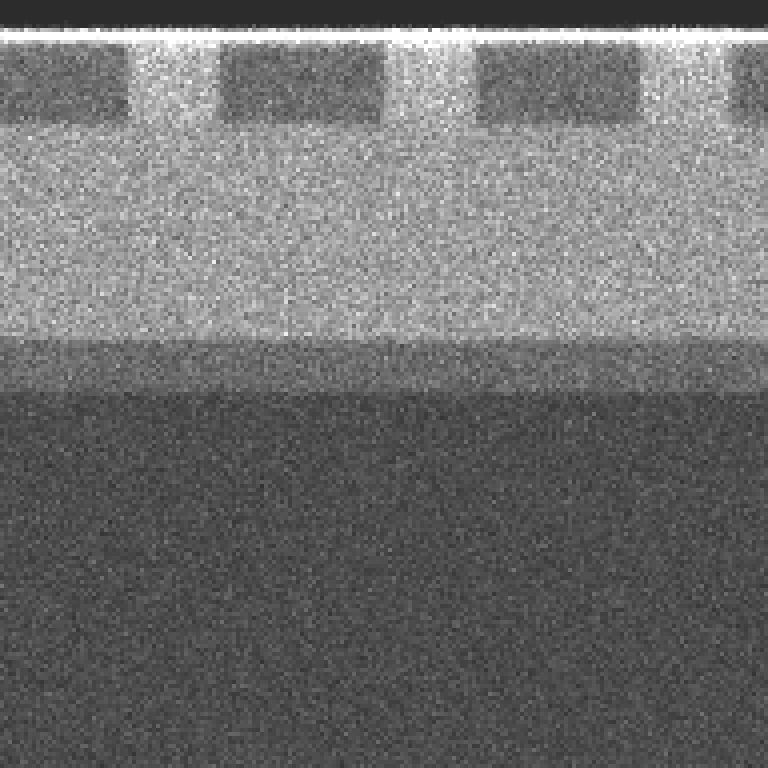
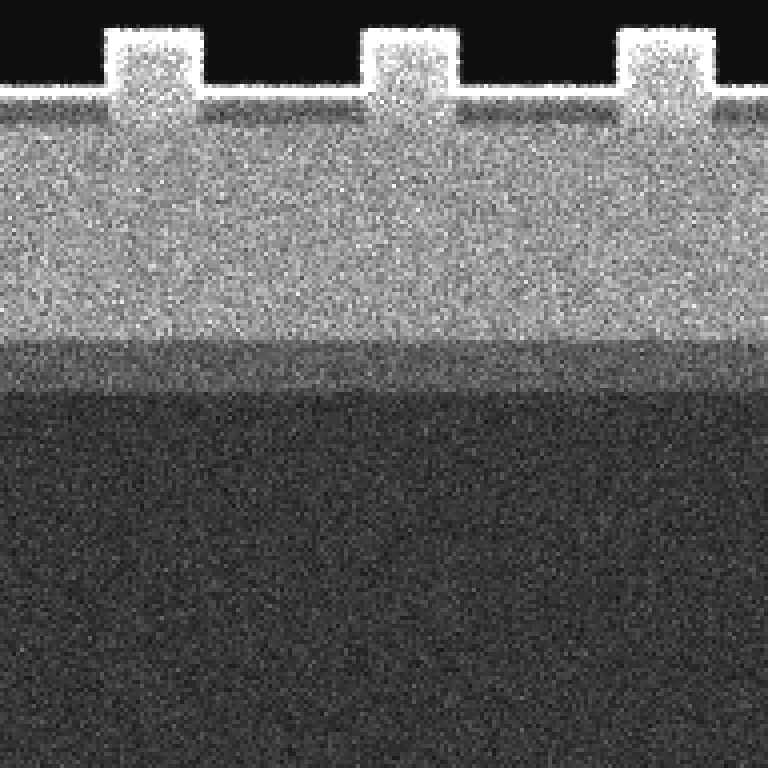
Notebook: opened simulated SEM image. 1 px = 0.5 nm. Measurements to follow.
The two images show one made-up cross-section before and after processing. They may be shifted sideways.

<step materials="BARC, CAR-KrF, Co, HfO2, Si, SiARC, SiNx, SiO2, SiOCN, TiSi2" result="removed SiNx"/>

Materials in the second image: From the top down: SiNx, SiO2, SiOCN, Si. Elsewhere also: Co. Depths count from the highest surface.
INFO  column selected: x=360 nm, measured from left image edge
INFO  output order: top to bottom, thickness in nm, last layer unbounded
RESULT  empty 28, SiNx 18, SiO2 108, SiOCN 26, Si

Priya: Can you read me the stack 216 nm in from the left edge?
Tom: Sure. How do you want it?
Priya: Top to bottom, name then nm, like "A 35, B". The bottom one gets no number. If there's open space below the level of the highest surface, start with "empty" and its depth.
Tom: Co 46, SiO2 108, SiOCN 26, Si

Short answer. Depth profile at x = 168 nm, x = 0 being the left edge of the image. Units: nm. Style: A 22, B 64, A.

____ empty 28, SiNx 18, SiO2 108, SiOCN 26, Si